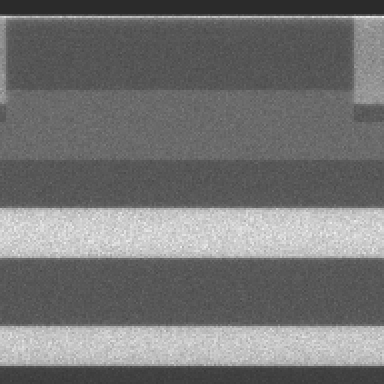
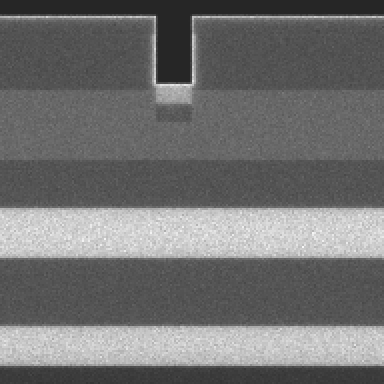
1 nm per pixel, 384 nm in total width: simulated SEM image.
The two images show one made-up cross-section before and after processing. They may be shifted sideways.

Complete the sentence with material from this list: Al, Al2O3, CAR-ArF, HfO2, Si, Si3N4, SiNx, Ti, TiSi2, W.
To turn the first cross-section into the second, W must be removed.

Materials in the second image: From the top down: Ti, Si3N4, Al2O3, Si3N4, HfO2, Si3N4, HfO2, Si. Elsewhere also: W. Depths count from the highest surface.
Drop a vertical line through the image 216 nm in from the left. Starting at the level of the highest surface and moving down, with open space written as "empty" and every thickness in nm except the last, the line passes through Ti 18, Si3N4 56, Al2O3 70, Si3N4 48, HfO2 50, Si3N4 68, HfO2 40, Si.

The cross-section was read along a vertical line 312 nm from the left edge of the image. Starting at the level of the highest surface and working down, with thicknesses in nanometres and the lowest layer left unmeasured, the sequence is Ti 18, Si3N4 56, Al2O3 70, Si3N4 48, HfO2 50, Si3N4 68, HfO2 40, Si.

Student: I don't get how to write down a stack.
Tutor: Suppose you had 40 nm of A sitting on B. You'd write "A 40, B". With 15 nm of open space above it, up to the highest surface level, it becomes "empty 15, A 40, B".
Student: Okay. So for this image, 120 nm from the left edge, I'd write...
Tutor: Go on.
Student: Ti 18, Si3N4 56, Al2O3 70, Si3N4 48, HfO2 50, Si3N4 68, HfO2 40, Si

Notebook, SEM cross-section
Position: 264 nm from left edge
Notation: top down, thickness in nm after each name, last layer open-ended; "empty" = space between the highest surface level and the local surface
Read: Ti 18, Si3N4 56, Al2O3 70, Si3N4 48, HfO2 50, Si3N4 68, HfO2 40, Si